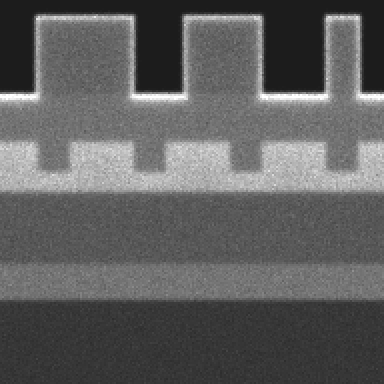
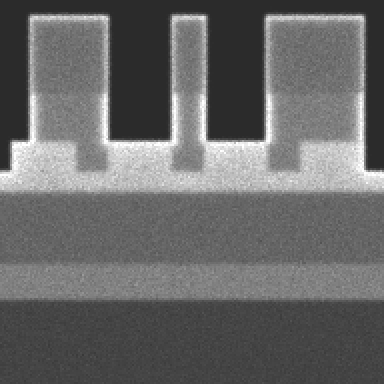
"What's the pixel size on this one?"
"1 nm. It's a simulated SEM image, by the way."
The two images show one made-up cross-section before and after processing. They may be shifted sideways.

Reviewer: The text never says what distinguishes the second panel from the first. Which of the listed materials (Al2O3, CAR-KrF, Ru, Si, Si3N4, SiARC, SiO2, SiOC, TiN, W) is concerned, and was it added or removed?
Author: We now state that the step removed SiO2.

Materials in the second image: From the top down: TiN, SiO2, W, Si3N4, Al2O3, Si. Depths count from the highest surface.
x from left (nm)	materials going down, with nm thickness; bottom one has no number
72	TiN 78, SiO2 48, W 50, Si3N4 72, Al2O3 36, Si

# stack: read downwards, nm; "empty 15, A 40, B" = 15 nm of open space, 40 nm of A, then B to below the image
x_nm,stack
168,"empty 126, W 50, Si3N4 72, Al2O3 36, Si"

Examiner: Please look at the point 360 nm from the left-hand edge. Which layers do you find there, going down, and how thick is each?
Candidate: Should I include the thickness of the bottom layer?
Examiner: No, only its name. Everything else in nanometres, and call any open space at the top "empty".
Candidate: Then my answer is TiN 78, SiO2 48, W 50, Si3N4 72, Al2O3 36, Si